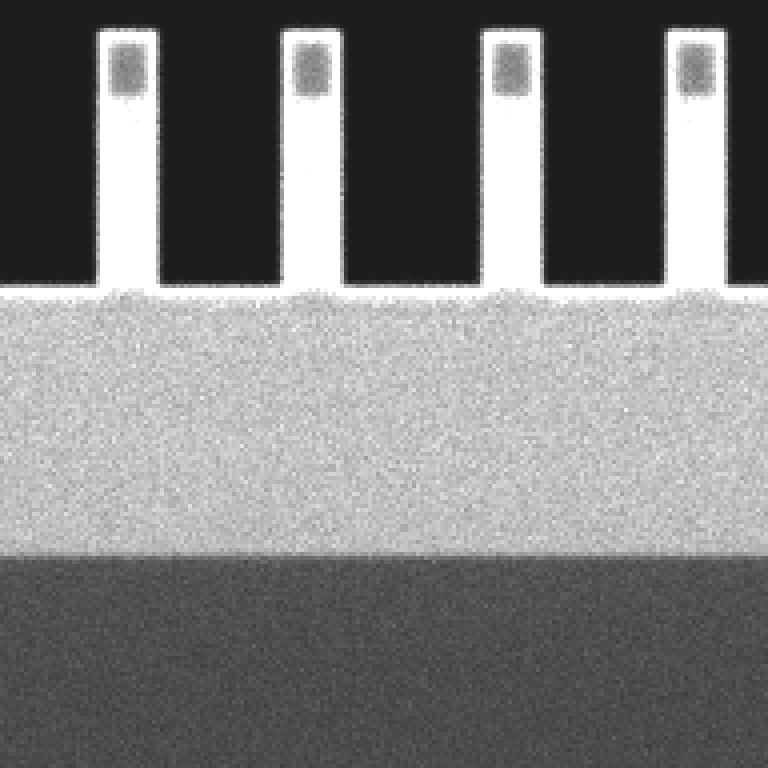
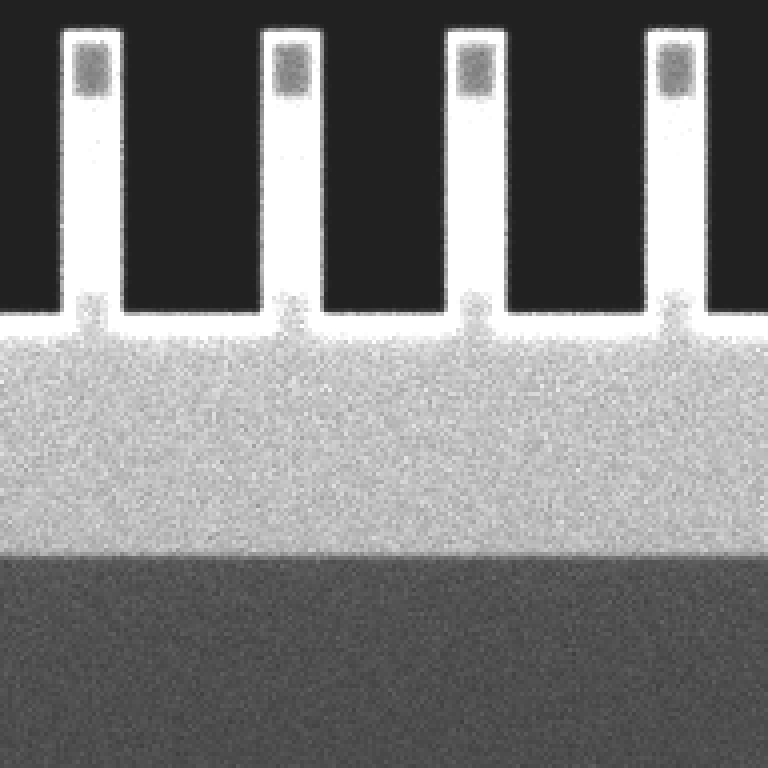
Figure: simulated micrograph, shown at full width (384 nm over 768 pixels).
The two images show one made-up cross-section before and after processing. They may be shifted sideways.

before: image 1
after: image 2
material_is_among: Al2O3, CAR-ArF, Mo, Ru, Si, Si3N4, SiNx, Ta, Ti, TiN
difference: TiN, removed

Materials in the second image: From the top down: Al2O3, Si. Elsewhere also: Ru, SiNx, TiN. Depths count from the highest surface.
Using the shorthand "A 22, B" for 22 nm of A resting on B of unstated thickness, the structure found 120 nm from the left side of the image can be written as empty 142, Al2O3 120, Si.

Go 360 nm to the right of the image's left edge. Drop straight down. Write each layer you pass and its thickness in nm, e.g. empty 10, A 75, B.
empty 142, Al2O3 120, Si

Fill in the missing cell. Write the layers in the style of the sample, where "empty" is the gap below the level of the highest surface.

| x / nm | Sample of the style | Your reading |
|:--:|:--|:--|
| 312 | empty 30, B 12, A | empty 142, Al2O3 120, Si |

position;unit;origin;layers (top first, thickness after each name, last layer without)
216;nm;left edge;empty 142, Al2O3 120, Si